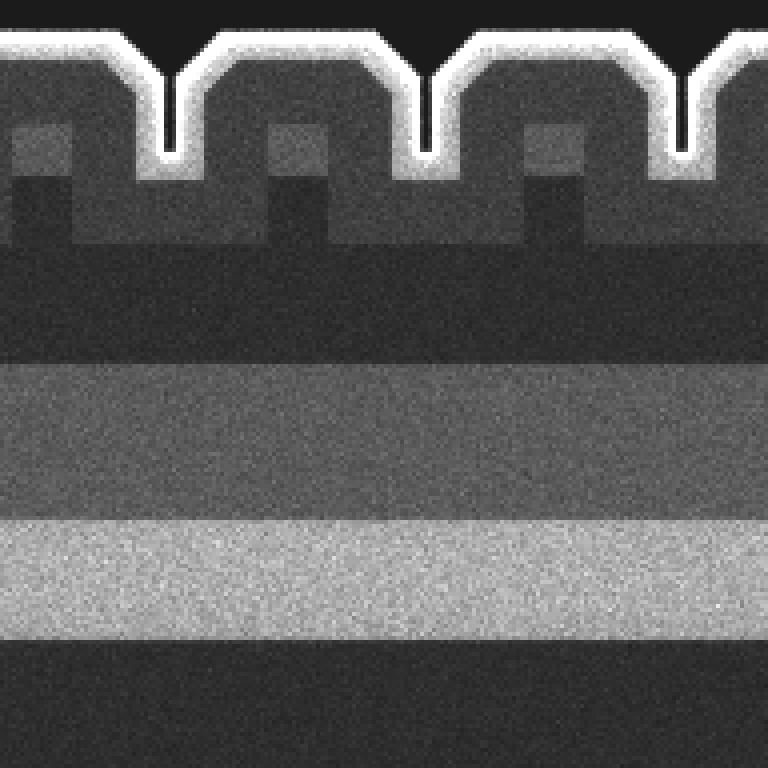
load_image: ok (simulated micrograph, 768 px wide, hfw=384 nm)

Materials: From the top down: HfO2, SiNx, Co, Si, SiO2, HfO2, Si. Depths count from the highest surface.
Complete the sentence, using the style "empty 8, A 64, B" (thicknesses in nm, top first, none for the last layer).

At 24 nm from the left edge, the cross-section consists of HfO2 14, SiNx 32, Co 26, Si 94, SiO2 78, HfO2 60, Si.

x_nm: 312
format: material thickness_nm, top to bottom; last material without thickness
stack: HfO2 20, SiNx 86, Si 60, SiO2 78, HfO2 60, Si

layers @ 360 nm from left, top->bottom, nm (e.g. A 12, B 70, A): empty 6, HfO2 22, SiNx 78, Si 60, SiO2 78, HfO2 60, Si